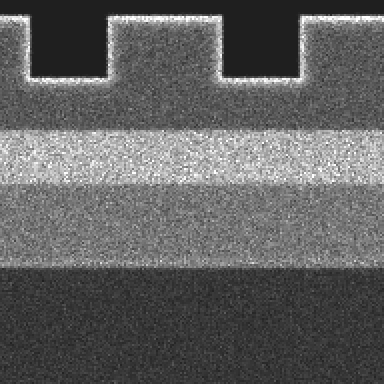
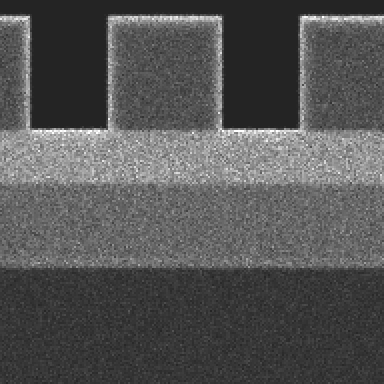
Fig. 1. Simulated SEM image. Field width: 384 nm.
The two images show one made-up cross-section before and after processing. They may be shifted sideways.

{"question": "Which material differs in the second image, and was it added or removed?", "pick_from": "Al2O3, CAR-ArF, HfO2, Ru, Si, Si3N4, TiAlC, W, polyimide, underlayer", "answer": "underlayer, removed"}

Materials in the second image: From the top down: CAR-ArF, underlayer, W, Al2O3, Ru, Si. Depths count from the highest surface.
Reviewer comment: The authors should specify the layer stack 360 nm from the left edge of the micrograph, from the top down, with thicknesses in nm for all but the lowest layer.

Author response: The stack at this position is CAR-ArF 62, underlayer 52, W 54, Al2O3 74, Ru 10, Si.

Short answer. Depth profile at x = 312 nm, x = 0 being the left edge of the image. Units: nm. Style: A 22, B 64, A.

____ CAR-ArF 62, underlayer 52, W 54, Al2O3 74, Ru 10, Si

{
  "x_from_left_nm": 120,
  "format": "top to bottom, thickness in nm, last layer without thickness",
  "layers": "CAR-ArF 62, underlayer 52, W 54, Al2O3 74, Ru 10, Si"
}